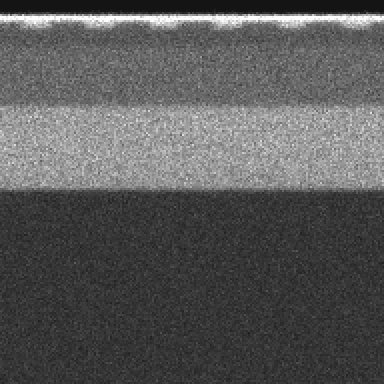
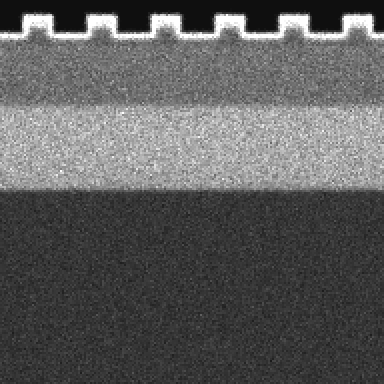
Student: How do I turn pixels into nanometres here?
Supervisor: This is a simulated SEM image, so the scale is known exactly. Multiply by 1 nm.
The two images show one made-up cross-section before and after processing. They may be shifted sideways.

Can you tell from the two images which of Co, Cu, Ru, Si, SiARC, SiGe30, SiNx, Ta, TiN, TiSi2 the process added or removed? Yes, it removed SiNx.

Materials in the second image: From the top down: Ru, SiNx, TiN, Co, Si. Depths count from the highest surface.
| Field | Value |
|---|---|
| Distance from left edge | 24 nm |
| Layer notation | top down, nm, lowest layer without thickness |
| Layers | Ru 12, SiNx 18, TiN 60, Co 84, Si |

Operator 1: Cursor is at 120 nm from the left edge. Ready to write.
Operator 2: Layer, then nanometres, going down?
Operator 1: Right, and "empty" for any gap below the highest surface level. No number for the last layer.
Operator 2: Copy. empty 18, SiNx 12, TiN 60, Co 84, Si